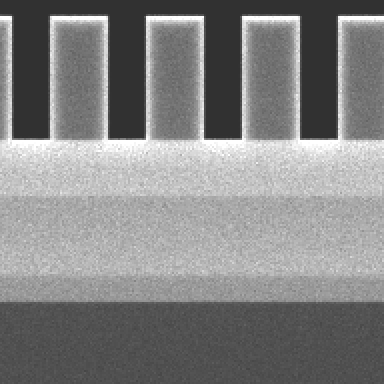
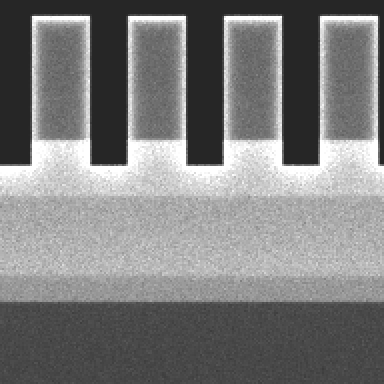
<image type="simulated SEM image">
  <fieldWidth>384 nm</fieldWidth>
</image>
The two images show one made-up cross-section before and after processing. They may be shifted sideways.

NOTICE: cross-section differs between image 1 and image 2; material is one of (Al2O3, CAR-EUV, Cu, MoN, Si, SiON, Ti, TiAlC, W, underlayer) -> removed: W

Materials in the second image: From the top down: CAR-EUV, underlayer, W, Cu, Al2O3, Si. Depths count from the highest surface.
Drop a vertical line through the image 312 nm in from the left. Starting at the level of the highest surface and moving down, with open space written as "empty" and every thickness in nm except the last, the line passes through empty 150, W 30, Cu 80, Al2O3 26, Si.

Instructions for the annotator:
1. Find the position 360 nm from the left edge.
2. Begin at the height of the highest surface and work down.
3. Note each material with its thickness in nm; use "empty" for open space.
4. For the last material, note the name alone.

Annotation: CAR-EUV 78, underlayer 46, W 56, Cu 80, Al2O3 26, Si